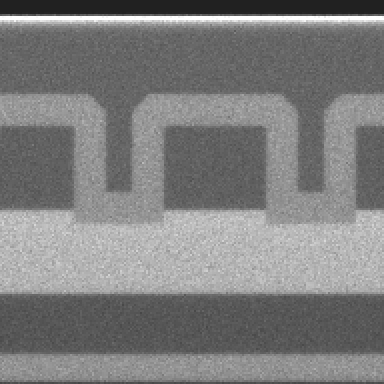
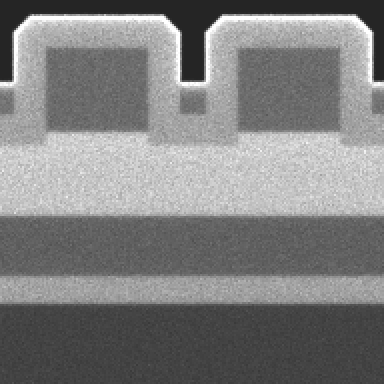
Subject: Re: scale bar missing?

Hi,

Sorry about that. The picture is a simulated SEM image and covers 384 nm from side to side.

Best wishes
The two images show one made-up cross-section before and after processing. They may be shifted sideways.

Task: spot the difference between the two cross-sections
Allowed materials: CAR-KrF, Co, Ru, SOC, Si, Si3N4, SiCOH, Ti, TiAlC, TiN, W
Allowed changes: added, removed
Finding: removed SOC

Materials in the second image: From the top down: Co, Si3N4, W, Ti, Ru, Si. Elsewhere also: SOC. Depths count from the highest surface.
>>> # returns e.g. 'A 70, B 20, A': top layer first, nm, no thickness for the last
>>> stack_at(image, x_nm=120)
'Co 32, Si3N4 84, W 84, Ti 60, Ru 28, Si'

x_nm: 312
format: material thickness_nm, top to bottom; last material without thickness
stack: Co 32, Si3N4 84, W 84, Ti 60, Ru 28, Si